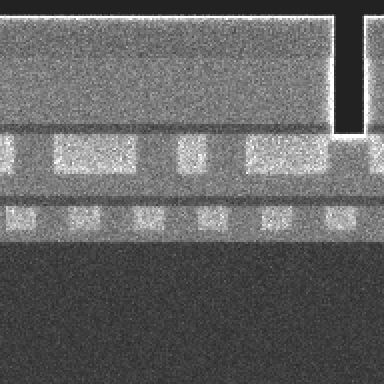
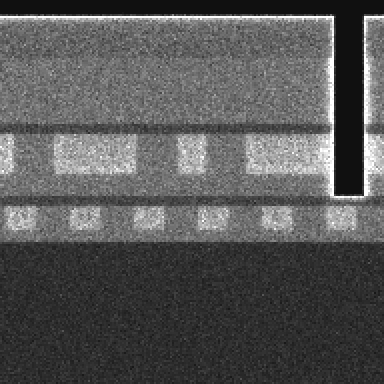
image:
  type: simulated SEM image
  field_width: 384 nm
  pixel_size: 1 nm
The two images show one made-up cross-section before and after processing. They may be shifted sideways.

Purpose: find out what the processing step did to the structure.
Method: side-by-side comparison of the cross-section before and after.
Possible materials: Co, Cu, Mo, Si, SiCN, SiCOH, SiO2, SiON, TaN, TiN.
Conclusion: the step removed SiO2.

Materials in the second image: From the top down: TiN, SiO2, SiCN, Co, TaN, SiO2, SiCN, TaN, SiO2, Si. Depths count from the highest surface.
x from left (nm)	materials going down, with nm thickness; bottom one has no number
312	TiN 42, SiO2 66, SiCN 10, Co 32, TaN 8, SiO2 22, SiCN 10, SiO2 36, Si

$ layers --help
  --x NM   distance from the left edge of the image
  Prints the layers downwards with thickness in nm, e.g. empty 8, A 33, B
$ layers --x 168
TiN 42, SiO2 66, SiCN 10, SiO2 62, SiCN 10, SiO2 36, Si